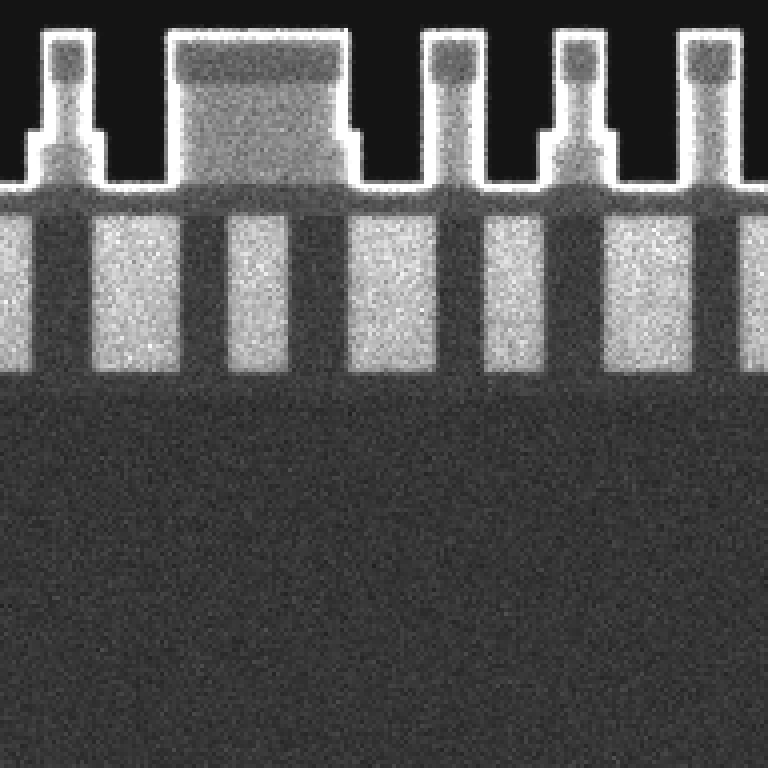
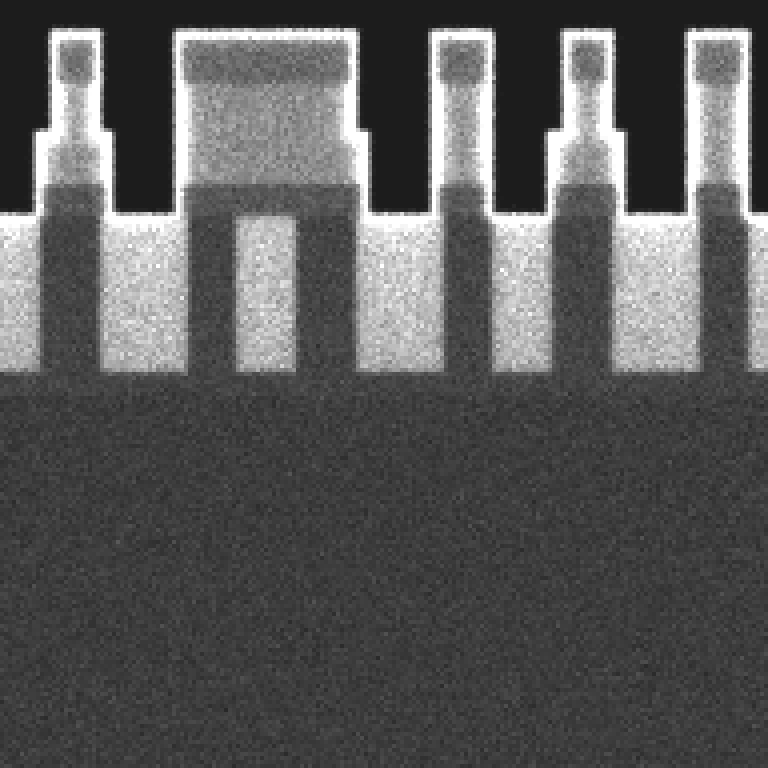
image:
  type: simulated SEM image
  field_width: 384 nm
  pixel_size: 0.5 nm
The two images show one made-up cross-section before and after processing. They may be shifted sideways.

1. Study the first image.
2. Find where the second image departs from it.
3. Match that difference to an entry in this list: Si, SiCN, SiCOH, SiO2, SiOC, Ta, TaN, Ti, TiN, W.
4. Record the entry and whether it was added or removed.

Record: SiCN / removed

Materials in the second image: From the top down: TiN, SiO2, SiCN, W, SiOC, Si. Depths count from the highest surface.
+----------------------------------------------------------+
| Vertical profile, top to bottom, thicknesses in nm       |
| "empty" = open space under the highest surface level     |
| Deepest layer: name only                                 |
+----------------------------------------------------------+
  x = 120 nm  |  TiN 26, SiO2 50, SiCN 16, W 78, SiOC 12, Si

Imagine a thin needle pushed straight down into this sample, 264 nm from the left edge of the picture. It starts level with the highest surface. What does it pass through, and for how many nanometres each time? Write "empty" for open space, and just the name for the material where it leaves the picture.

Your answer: empty 92, W 78, SiOC 12, Si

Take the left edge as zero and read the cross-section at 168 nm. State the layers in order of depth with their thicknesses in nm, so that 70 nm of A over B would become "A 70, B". TiN 26, SiO2 50, SiCN 16, SiOC 90, Si